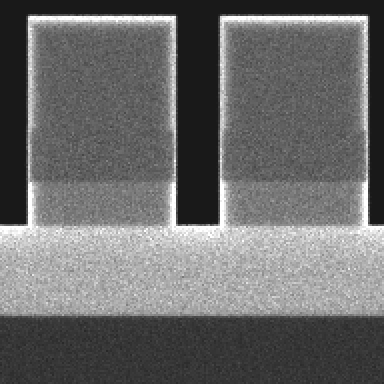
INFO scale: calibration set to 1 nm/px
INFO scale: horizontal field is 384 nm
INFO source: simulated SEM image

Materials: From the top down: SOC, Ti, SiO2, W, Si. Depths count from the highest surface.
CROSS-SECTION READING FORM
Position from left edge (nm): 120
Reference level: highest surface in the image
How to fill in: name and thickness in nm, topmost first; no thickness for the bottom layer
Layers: SOC 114, Ti 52, SiO2 44, W 90, Si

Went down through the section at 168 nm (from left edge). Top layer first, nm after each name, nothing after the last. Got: SOC 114, Ti 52, SiO2 44, W 90, Si